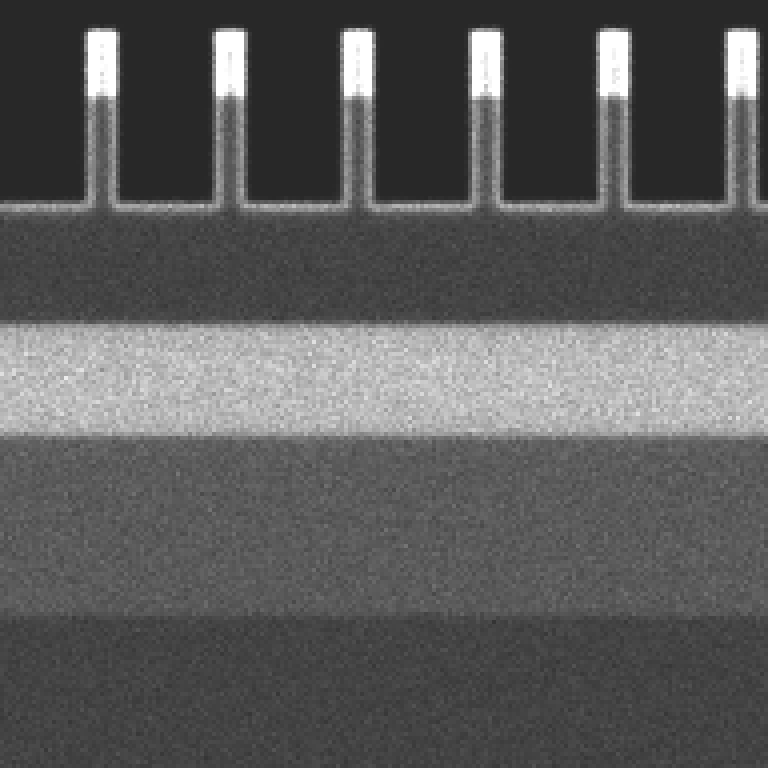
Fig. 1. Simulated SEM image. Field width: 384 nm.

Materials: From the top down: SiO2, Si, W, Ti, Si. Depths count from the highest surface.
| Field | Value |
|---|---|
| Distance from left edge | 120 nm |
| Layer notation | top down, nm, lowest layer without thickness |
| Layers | SiO2 32, Si 114, W 56, Ti 90, Si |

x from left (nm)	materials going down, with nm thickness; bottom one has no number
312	SiO2 32, Si 114, W 56, Ti 90, Si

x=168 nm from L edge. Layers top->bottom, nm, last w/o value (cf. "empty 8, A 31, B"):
empty 86, Si 60, W 56, Ti 90, Si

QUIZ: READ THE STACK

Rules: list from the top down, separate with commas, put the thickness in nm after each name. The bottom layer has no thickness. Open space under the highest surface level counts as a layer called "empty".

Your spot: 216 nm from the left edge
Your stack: empty 86, Si 60, W 56, Ti 90, Si